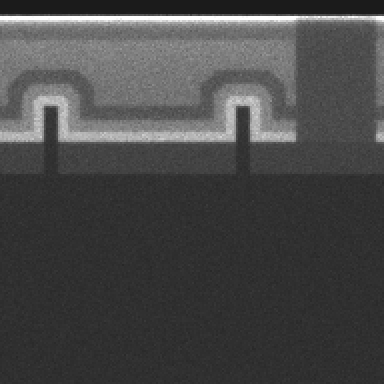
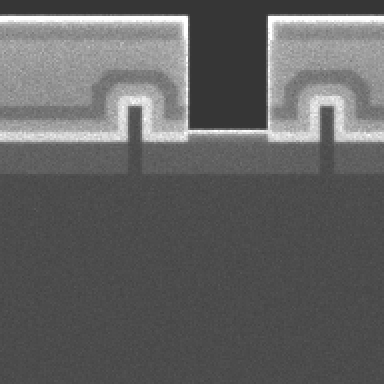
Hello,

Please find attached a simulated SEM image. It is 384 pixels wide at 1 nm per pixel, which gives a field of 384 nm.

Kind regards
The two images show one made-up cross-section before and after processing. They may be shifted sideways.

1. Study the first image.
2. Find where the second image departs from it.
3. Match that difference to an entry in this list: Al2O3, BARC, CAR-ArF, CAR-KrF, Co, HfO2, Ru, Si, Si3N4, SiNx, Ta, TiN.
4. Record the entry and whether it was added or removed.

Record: Si3N4 / removed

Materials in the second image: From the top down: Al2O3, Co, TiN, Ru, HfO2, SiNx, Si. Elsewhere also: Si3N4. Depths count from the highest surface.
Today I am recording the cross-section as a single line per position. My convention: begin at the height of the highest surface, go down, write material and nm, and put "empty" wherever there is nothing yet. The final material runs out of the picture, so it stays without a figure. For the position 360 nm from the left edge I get Al2O3 24, Co 38, TiN 42, Ru 12, HfO2 10, SiNx 32, Si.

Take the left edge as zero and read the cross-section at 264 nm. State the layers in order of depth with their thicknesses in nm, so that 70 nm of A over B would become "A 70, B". empty 114, Si3N4 12, SiNx 32, Si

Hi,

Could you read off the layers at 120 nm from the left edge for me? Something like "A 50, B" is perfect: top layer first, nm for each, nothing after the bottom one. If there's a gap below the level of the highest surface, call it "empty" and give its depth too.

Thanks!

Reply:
Al2O3 24, Co 30, TiN 14, Ru 14, HfO2 44, SiNx 32, Si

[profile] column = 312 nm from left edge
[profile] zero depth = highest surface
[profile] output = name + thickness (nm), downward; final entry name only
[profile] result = Al2O3 24, Co 30, TiN 14, Ru 14, HfO2 44, SiNx 32, Si